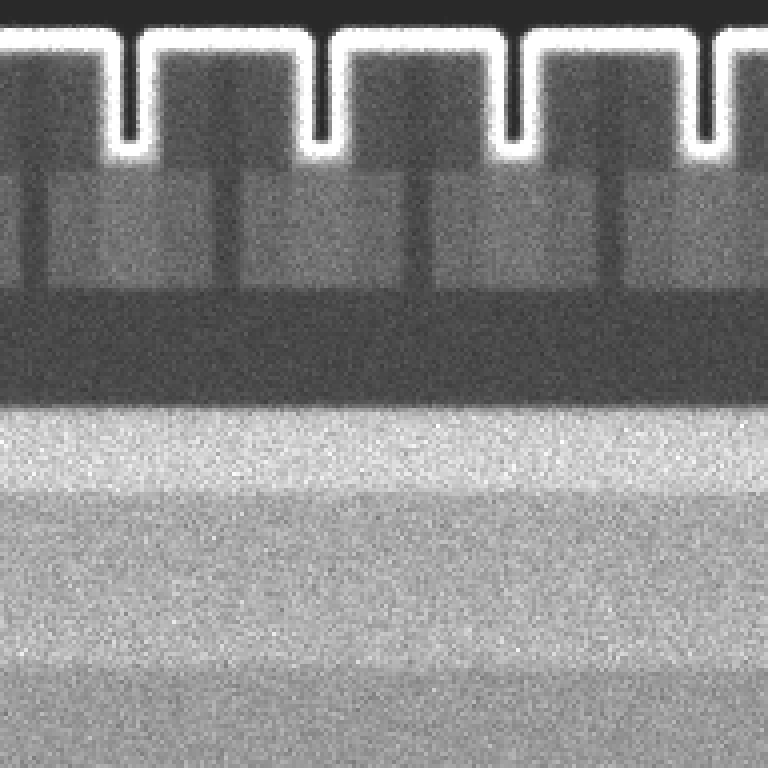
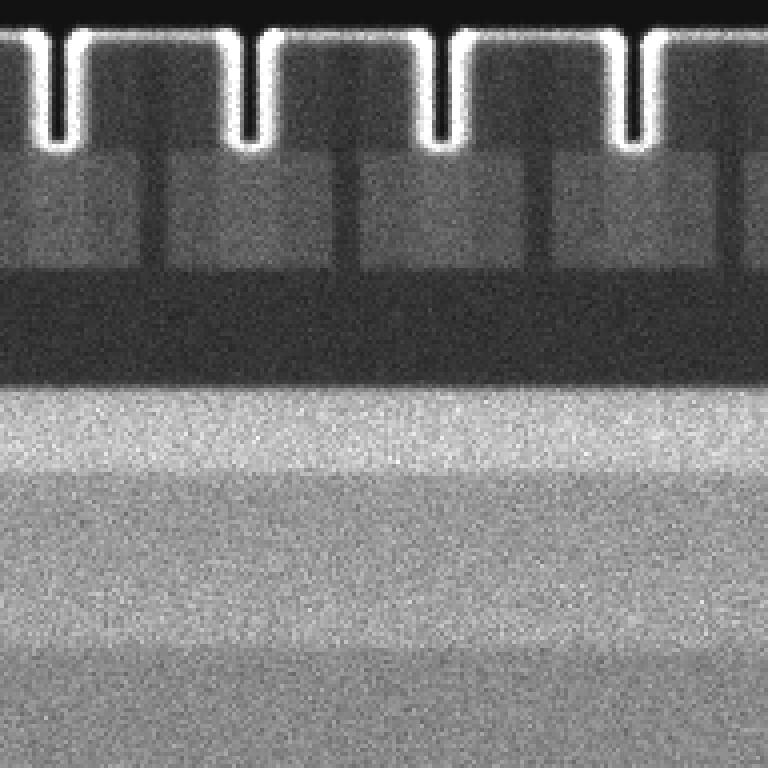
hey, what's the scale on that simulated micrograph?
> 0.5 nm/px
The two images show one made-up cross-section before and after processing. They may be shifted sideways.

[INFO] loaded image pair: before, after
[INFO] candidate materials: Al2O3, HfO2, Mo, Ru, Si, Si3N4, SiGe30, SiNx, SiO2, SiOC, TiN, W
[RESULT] removed Al2O3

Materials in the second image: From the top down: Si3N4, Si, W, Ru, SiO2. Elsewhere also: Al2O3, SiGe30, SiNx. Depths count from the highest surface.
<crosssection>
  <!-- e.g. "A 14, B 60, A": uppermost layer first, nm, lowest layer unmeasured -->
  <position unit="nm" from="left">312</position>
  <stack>empty 56, Si3N4 62, Si 60, W 42, Ru 88, SiO2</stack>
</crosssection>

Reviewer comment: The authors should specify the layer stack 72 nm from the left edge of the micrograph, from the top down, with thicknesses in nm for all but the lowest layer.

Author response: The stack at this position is Si 178, W 42, Ru 88, SiO2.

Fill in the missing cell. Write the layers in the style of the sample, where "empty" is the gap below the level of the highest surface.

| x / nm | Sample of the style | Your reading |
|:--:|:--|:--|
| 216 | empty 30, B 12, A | empty 56, Si3N4 62, Si 60, W 42, Ru 88, SiO2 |